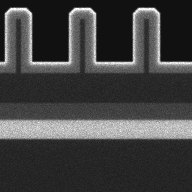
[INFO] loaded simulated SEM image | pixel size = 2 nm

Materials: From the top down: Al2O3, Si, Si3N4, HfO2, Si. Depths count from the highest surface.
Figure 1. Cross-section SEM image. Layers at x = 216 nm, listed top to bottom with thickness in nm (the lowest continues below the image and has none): empty 108, Al2O3 22, Si 60, Si3N4 34, HfO2 38, Si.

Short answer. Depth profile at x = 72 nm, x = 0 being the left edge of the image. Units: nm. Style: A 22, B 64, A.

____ empty 108, Al2O3 22, Si 60, Si3N4 34, HfO2 38, Si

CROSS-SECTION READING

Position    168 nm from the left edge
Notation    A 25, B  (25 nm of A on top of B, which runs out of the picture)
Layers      Al2O3 22, Si 168, Si3N4 34, HfO2 38, Si